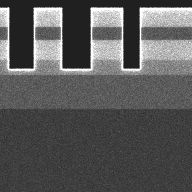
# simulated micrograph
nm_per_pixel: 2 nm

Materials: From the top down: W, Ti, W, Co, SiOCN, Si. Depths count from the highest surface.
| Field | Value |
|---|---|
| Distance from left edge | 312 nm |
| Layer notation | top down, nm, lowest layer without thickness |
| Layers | W 38, Ti 26, W 40, Co 30, SiOCN 68, Si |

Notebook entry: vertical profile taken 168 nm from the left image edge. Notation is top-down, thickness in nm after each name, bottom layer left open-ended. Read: empty 122, Co 12, SiOCN 68, Si